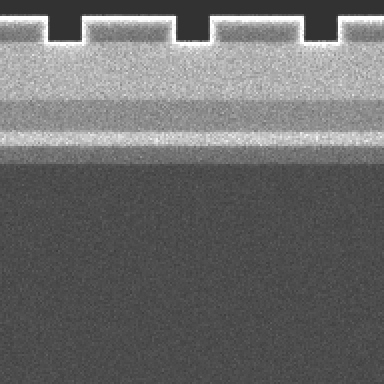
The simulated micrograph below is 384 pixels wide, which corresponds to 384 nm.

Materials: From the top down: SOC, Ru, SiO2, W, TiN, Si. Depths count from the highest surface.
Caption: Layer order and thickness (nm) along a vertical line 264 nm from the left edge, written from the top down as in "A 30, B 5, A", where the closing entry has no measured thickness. SOC 26, Ru 58, SiO2 32, W 14, TiN 18, Si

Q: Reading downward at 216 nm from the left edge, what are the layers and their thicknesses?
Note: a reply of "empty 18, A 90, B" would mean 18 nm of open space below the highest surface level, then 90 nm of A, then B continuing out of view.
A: SOC 26, Ru 58, SiO2 32, W 14, TiN 18, Si